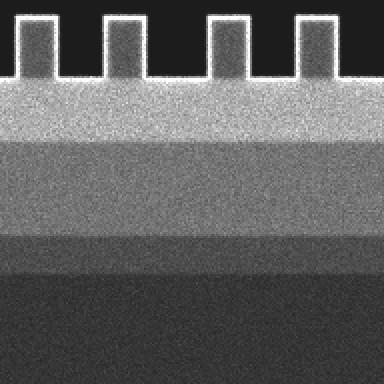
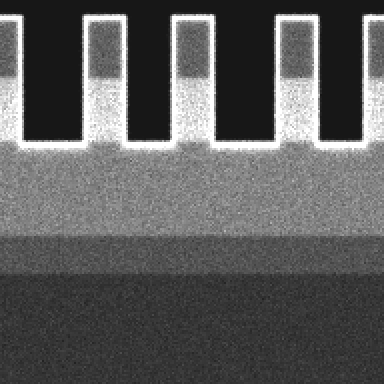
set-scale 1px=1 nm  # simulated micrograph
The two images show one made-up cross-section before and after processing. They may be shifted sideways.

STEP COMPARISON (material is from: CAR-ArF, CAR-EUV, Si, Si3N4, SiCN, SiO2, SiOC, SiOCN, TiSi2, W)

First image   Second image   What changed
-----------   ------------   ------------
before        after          W, removed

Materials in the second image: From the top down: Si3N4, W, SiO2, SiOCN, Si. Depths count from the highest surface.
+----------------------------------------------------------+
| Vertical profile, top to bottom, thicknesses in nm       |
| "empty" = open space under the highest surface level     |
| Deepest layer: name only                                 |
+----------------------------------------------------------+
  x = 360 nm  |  empty 126, SiO2 94, SiOCN 38, Si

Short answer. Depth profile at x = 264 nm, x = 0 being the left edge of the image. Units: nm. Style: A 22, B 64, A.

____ empty 126, SiO2 94, SiOCN 38, Si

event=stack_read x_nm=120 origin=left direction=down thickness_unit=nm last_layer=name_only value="Si3N4 62, W 64, SiO2 94, SiOCN 38, Si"